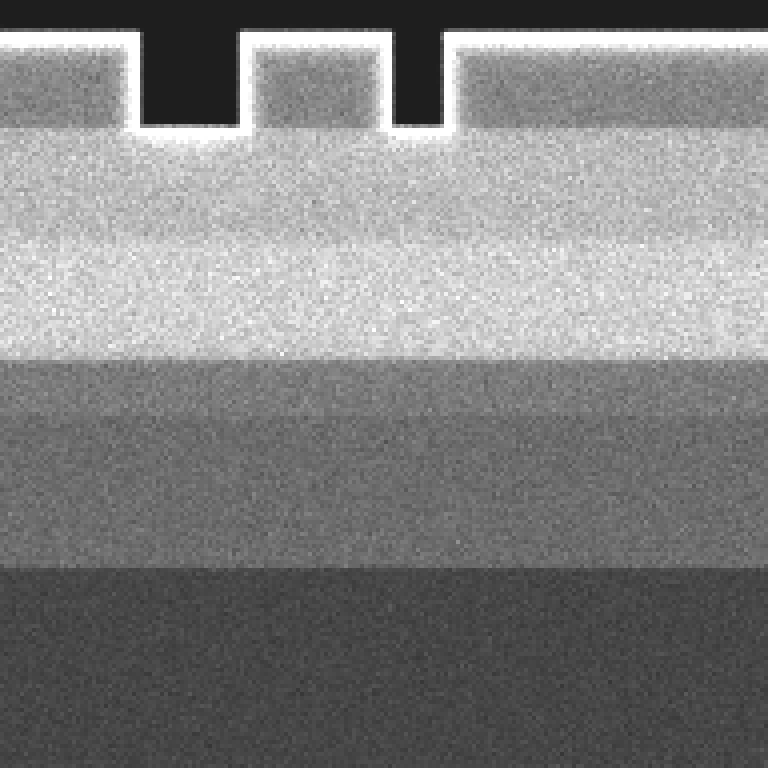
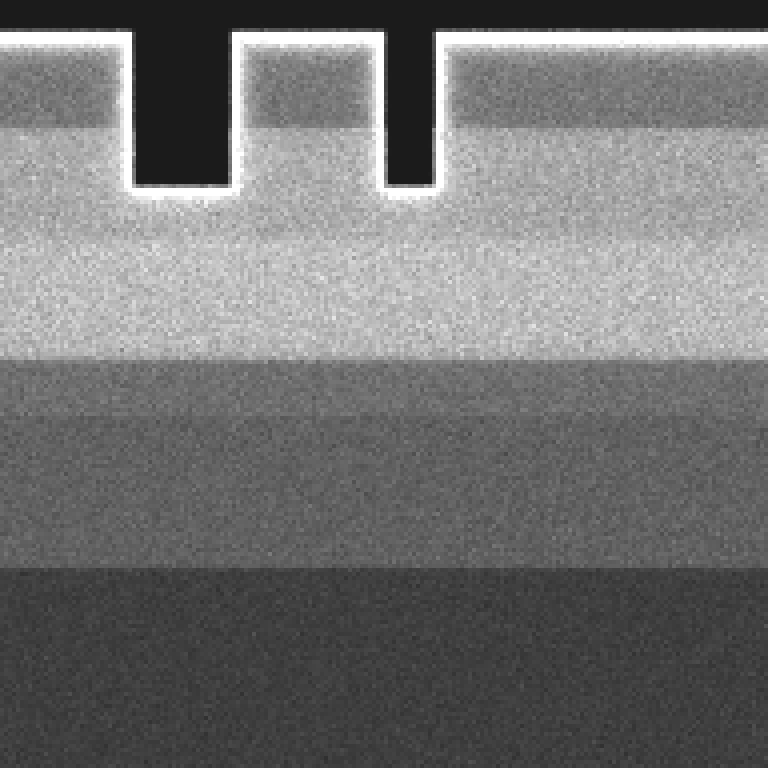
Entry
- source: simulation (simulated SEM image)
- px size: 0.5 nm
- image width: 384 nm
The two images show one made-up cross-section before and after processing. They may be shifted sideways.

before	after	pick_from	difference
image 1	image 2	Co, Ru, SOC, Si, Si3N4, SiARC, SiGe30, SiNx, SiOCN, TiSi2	Co removed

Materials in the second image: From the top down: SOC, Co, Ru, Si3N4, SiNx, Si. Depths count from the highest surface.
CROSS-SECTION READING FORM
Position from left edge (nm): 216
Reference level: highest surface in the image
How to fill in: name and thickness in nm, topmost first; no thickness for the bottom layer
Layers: empty 78, Co 26, Ru 60, Si3N4 28, SiNx 76, Si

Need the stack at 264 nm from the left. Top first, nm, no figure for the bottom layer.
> SOC 48, Co 56, Ru 60, Si3N4 28, SiNx 76, Si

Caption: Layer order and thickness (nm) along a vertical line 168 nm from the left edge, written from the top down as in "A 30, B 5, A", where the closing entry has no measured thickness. SOC 48, Co 56, Ru 60, Si3N4 28, SiNx 76, Si